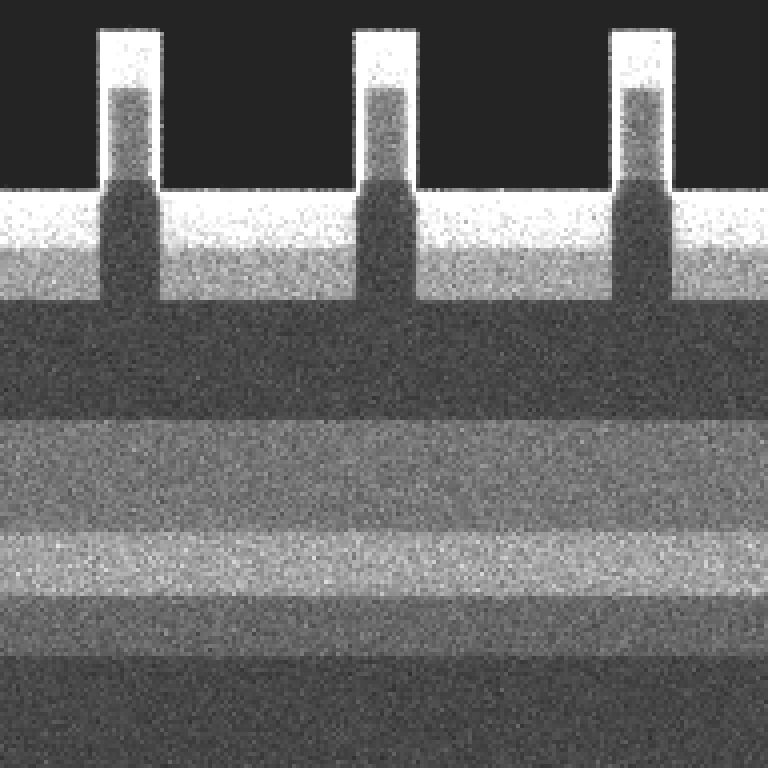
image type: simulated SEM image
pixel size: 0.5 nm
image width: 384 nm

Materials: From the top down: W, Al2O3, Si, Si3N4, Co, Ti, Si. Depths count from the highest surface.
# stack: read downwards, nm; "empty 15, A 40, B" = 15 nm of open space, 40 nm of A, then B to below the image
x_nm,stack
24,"empty 80, W 28, Al2O3 26, Si 60, Si3N4 56, Co 32, Ti 30, Si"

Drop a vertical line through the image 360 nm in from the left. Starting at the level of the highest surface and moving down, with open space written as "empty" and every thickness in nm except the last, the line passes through empty 80, W 28, Al2O3 26, Si 60, Si3N4 56, Co 32, Ti 30, Si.